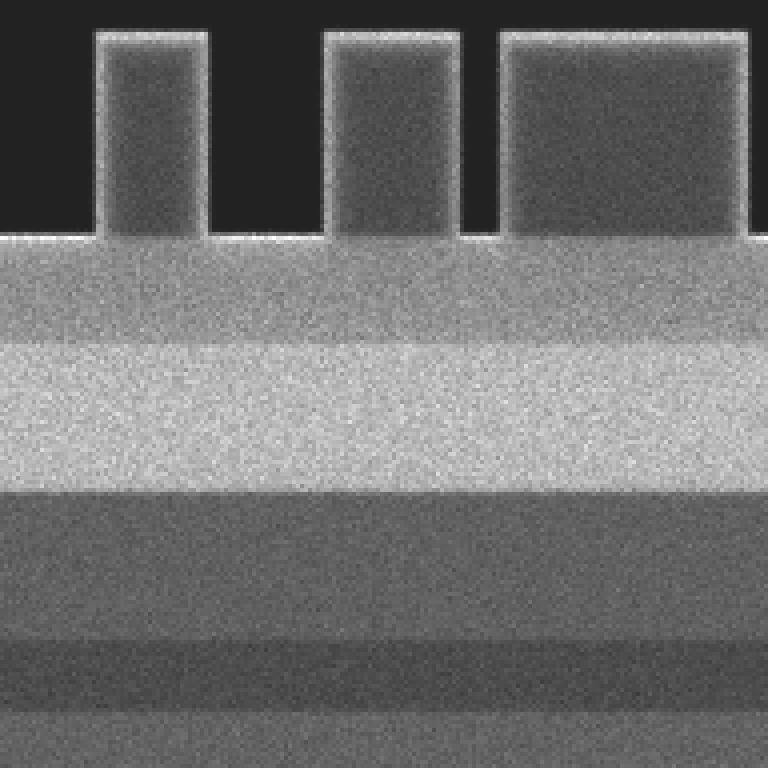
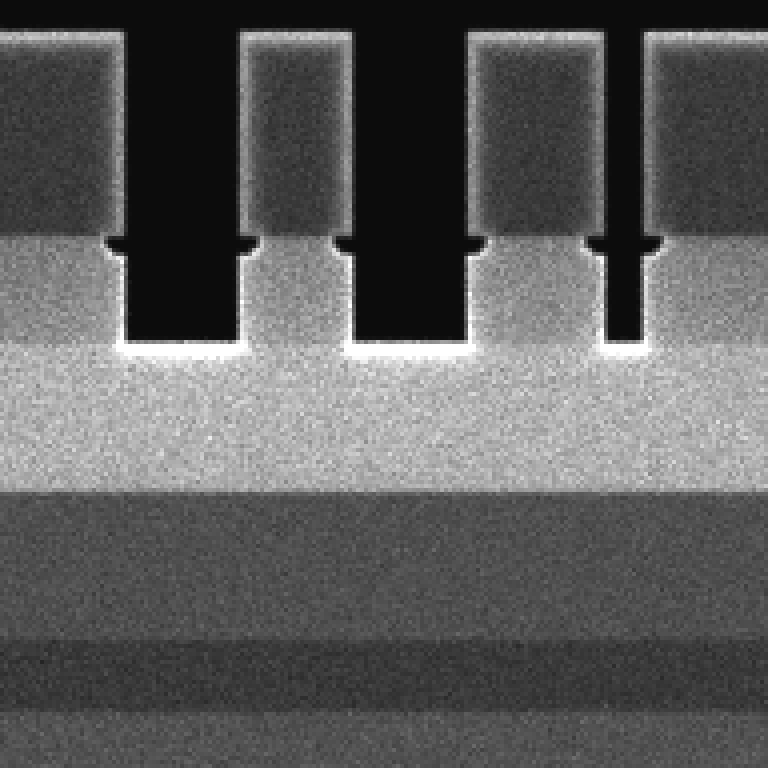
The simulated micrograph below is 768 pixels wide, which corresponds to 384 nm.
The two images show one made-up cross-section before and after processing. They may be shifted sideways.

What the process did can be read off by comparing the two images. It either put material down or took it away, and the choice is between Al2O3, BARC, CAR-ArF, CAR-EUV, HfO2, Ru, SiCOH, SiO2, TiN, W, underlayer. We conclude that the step removed W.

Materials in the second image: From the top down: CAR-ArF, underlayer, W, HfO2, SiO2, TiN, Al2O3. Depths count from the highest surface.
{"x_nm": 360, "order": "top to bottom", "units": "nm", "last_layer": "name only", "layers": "CAR-ArF 66, underlayer 36, W 54, HfO2 74, SiO2 74, TiN 36, Al2O3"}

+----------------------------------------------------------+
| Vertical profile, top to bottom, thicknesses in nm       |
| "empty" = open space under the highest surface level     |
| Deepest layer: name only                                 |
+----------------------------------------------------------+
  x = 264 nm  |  CAR-ArF 66, underlayer 36, W 54, HfO2 74, SiO2 74, TiN 36, Al2O3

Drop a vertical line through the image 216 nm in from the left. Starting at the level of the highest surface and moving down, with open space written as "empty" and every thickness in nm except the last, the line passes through empty 156, HfO2 74, SiO2 74, TiN 36, Al2O3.